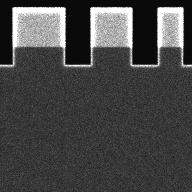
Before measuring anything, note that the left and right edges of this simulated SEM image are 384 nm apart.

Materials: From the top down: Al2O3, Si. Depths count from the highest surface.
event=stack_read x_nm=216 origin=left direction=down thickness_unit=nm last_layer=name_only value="Al2O3 78, Si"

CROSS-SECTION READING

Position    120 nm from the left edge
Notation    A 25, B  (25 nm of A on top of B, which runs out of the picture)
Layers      Al2O3 78, Si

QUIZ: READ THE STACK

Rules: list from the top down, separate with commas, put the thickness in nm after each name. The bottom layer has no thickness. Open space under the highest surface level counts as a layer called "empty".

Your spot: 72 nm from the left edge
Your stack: Al2O3 78, Si